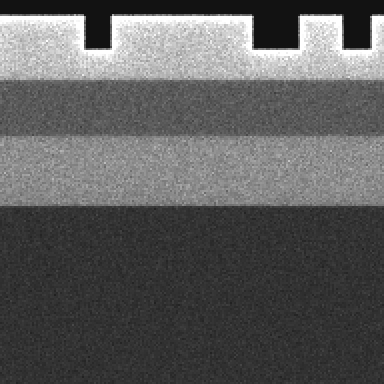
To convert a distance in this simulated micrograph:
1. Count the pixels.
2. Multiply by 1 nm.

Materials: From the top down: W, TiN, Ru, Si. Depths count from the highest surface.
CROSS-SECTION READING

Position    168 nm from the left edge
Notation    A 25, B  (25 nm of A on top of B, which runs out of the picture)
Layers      W 64, TiN 56, Ru 70, Si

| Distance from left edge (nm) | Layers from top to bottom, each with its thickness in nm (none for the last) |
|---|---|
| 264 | empty 34, W 30, TiN 56, Ru 70, Si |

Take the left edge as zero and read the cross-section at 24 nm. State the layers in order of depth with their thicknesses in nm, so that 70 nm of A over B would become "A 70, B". W 64, TiN 56, Ru 70, Si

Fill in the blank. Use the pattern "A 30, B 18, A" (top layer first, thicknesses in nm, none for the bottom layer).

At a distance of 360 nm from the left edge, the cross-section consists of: empty 34, W 30, TiN 56, Ru 70, Si